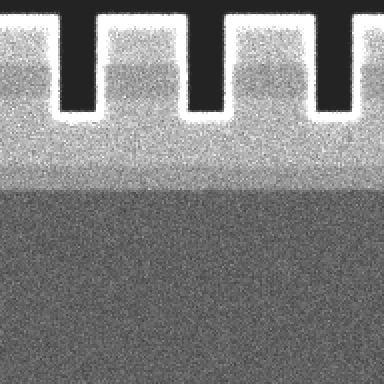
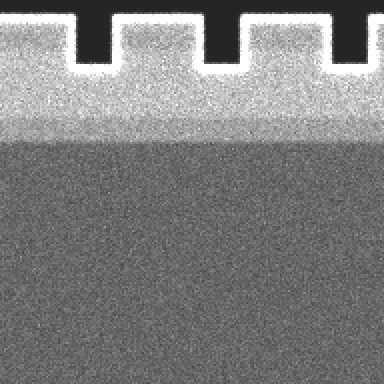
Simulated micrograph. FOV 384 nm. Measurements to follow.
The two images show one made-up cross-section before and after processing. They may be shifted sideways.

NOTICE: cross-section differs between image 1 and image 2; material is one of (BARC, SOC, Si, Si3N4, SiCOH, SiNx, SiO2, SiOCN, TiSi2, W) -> removed: SOC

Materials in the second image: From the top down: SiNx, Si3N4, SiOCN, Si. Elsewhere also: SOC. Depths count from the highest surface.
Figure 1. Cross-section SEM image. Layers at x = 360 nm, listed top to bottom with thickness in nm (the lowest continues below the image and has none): empty 50, Si3N4 52, SiOCN 24, Si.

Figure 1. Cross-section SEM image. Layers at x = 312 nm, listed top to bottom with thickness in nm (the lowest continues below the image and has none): SiNx 34, Si3N4 68, SiOCN 24, Si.